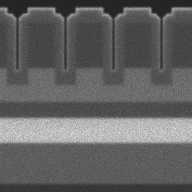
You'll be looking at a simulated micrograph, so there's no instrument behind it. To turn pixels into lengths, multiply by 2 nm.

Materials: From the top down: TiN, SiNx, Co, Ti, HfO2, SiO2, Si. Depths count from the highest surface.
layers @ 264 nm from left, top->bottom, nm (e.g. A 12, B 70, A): TiN 30, SiNx 90, Co 68, Ti 32, HfO2 50, SiO2 82, Si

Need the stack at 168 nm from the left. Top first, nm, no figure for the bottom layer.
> TiN 30, SiNx 90, Co 68, Ti 32, HfO2 50, SiO2 82, Si